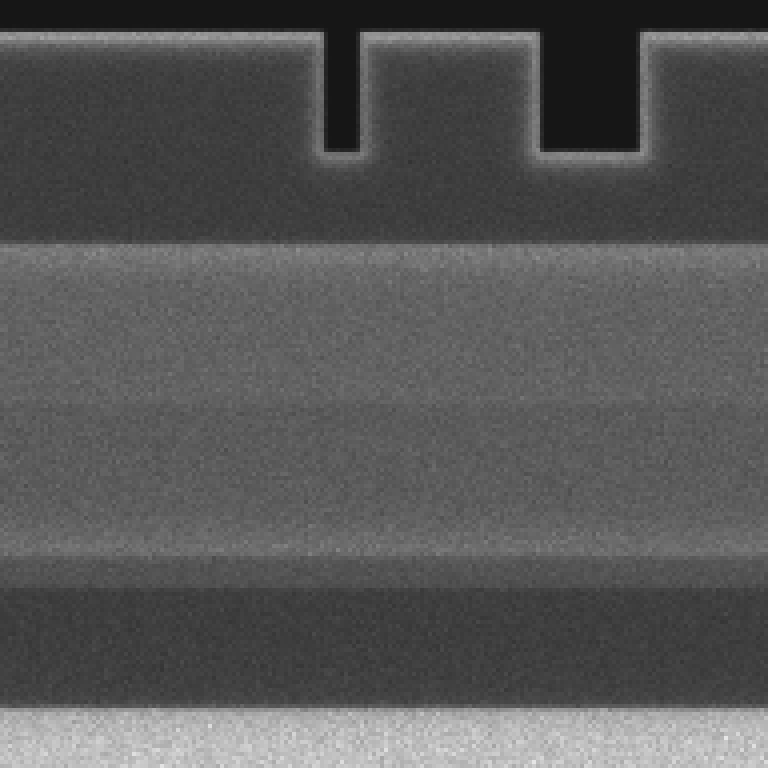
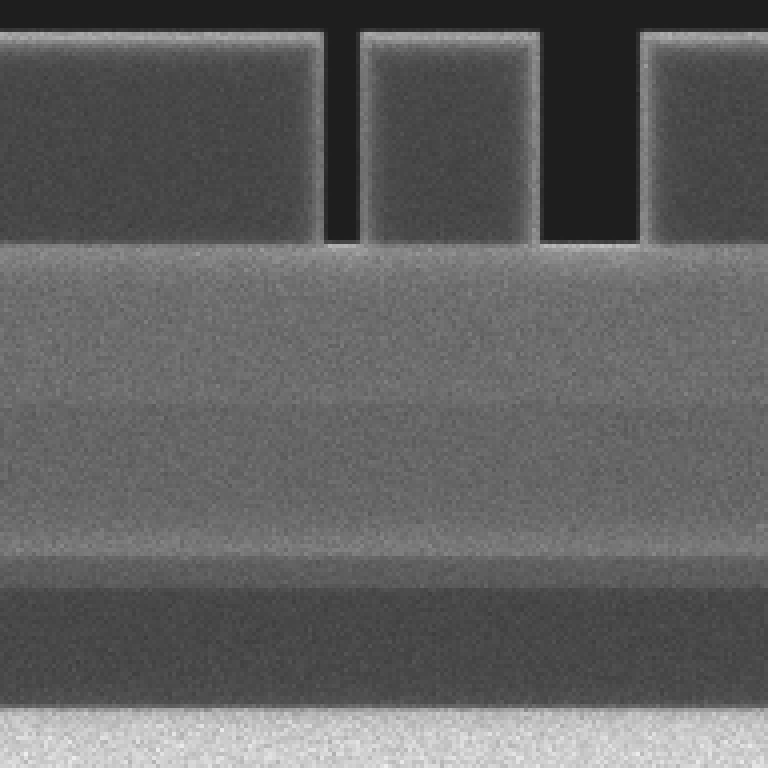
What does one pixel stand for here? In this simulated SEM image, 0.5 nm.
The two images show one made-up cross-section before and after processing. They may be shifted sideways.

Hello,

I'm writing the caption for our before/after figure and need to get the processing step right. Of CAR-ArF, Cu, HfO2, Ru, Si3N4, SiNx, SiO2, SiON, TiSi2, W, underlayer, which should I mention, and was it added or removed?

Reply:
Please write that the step removed underlayer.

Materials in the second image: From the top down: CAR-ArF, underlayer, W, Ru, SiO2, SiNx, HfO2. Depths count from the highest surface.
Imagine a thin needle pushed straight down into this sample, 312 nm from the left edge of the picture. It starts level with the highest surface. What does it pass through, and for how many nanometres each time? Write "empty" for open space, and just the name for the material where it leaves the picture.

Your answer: empty 106, W 80, Ru 76, SiO2 16, SiNx 60, HfO2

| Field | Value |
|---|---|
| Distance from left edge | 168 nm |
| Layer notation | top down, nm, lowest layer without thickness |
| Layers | empty 106, W 80, Ru 76, SiO2 16, SiNx 60, HfO2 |